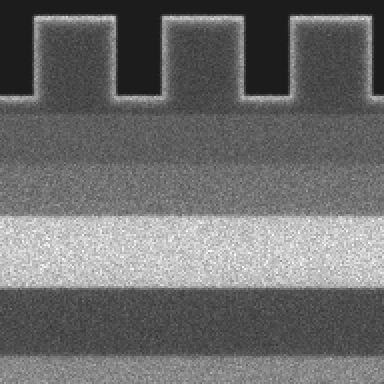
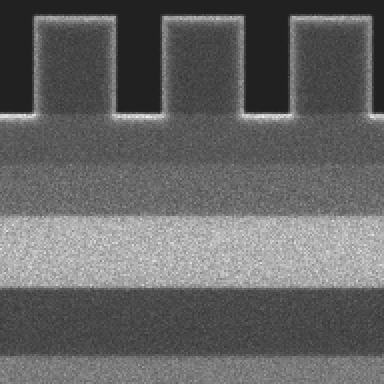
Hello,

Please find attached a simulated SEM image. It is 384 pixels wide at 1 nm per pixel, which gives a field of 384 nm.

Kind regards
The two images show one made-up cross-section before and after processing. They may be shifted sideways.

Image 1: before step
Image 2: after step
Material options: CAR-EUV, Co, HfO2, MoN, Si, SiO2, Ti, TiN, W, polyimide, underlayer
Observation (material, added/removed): underlayer, removed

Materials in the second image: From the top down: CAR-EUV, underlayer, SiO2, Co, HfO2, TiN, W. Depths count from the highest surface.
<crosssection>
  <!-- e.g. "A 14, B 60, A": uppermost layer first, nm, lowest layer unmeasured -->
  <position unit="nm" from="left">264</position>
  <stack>empty 98, SiO2 50, Co 52, HfO2 72, TiN 68, W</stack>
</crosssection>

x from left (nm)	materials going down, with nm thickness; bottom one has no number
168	CAR-EUV 80, underlayer 18, SiO2 50, Co 52, HfO2 72, TiN 68, W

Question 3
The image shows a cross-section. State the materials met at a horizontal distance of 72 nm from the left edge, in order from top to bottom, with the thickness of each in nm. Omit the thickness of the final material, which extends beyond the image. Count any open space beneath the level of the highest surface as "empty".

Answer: CAR-EUV 80, underlayer 18, SiO2 50, Co 52, HfO2 72, TiN 68, W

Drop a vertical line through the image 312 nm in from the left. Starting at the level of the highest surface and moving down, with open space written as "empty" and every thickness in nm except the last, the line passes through CAR-EUV 80, underlayer 18, SiO2 50, Co 52, HfO2 72, TiN 68, W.